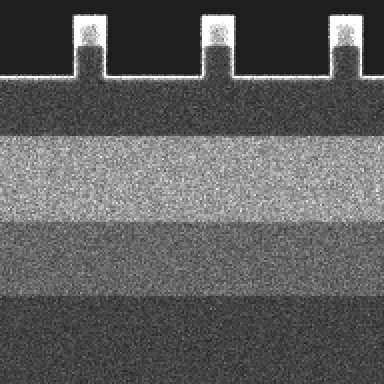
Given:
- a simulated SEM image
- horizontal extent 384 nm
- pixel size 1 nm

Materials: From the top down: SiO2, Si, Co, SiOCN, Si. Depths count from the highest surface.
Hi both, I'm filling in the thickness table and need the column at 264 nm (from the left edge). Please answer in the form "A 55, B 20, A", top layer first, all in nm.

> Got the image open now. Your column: empty 60, Si 60, Co 86, SiOCN 74, Si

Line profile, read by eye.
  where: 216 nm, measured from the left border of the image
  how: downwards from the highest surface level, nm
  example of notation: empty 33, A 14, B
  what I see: SiO2 30, Si 90, Co 86, SiOCN 74, Si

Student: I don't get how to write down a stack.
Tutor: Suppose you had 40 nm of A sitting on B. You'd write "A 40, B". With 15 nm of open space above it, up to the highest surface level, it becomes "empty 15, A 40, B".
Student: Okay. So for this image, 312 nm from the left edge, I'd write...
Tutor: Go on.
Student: empty 60, Si 60, Co 86, SiOCN 74, Si